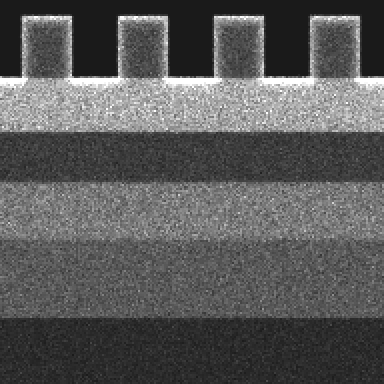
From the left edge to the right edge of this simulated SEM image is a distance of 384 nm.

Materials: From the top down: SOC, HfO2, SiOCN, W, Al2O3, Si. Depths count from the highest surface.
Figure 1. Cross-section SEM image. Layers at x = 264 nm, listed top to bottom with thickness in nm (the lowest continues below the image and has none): empty 62, HfO2 54, SiOCN 50, W 58, Al2O3 78, Si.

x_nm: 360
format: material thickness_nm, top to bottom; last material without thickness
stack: empty 62, HfO2 54, SiOCN 50, W 58, Al2O3 78, Si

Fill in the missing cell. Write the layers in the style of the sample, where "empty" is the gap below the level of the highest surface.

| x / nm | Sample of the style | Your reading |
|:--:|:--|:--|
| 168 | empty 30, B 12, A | empty 62, HfO2 54, SiOCN 50, W 58, Al2O3 78, Si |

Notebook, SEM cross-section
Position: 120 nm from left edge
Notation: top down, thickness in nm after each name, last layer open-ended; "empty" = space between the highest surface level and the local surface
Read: SOC 62, HfO2 54, SiOCN 50, W 58, Al2O3 78, Si